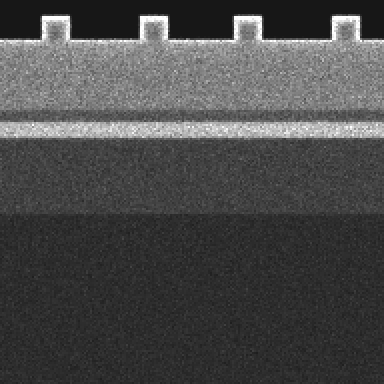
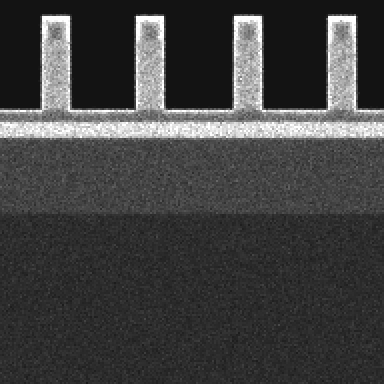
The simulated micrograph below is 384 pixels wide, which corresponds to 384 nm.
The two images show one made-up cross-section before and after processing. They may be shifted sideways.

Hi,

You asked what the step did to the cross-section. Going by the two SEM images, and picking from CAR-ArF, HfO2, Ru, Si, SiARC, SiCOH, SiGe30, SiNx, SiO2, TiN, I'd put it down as Ru, removed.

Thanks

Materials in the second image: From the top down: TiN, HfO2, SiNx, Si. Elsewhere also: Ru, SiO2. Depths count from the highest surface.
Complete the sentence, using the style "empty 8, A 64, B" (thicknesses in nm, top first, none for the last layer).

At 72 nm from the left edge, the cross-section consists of empty 94, TiN 12, HfO2 16, SiNx 76, Si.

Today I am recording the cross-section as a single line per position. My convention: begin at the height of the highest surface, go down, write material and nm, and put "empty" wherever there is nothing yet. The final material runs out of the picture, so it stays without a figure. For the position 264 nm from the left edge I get empty 94, TiN 12, HfO2 16, SiNx 76, Si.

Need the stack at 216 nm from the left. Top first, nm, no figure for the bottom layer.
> empty 94, TiN 12, HfO2 16, SiNx 76, Si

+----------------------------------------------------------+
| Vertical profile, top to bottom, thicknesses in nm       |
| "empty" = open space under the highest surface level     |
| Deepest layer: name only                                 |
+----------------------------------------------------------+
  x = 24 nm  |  empty 94, TiN 12, HfO2 16, SiNx 76, Si